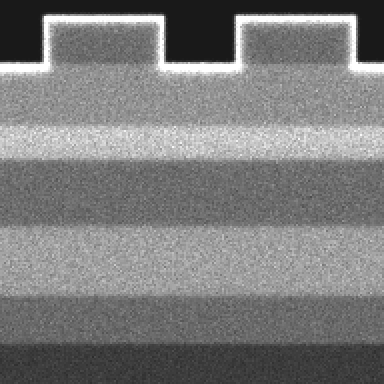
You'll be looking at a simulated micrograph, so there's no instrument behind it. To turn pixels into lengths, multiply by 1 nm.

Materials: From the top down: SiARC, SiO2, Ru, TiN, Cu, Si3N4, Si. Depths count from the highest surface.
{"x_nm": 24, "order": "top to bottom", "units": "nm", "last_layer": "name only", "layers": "empty 48, SiO2 62, Ru 34, TiN 66, Cu 70, Si3N4 48, Si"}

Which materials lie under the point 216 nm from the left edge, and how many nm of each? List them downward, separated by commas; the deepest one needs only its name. empty 48, SiO2 62, Ru 34, TiN 66, Cu 70, Si3N4 48, Si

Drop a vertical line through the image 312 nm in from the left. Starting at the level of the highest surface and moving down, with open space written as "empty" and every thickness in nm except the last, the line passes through SiARC 48, SiO2 62, Ru 34, TiN 66, Cu 70, Si3N4 48, Si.